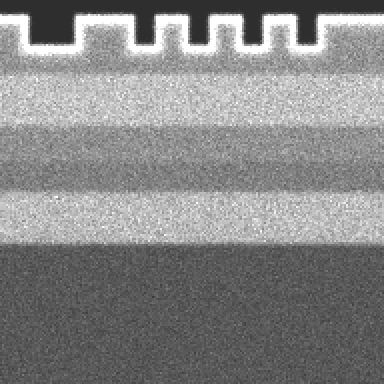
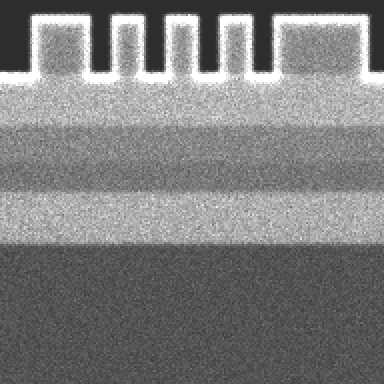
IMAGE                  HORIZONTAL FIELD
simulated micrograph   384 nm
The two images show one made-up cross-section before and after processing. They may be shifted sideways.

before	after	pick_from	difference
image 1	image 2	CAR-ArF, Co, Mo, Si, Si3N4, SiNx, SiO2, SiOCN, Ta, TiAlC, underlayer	underlayer removed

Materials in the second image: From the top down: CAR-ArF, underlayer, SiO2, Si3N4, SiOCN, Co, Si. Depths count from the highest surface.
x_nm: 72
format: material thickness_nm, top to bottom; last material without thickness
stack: CAR-ArF 30, underlayer 28, SiO2 52, Si3N4 36, SiOCN 30, Co 52, Si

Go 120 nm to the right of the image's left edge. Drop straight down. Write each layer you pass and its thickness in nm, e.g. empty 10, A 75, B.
CAR-ArF 30, underlayer 28, SiO2 52, Si3N4 36, SiOCN 30, Co 52, Si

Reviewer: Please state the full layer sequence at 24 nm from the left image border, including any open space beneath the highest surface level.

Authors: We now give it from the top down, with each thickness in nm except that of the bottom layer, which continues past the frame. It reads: empty 58, SiO2 52, Si3N4 36, SiOCN 30, Co 52, Si